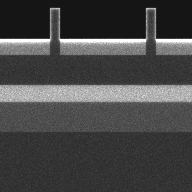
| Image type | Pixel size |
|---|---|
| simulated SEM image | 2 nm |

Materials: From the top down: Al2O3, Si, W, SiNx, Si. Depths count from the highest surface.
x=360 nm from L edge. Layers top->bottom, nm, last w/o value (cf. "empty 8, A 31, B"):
empty 62, Al2O3 32, Si 60, W 34, SiNx 60, Si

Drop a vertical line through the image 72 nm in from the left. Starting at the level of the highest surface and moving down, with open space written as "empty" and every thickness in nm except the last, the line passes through empty 62, Al2O3 32, Si 60, W 34, SiNx 60, Si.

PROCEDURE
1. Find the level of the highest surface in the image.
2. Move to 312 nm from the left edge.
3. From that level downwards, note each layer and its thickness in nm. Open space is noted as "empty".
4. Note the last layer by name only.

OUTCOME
empty 62, Al2O3 32, Si 60, W 34, SiNx 60, Si